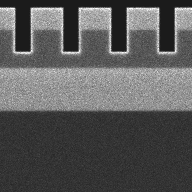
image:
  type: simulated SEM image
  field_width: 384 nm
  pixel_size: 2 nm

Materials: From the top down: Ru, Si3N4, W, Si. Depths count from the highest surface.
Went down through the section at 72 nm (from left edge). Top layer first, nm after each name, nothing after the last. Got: Ru 44, Si3N4 76, W 86, Si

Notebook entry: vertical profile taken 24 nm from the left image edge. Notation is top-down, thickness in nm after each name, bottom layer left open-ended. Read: Ru 44, Si3N4 76, W 86, Si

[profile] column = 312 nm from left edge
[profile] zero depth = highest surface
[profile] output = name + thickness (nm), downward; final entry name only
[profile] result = Ru 44, Si3N4 76, W 86, Si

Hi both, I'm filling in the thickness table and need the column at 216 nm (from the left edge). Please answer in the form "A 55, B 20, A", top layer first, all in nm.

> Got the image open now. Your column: Ru 44, Si3N4 76, W 86, Si